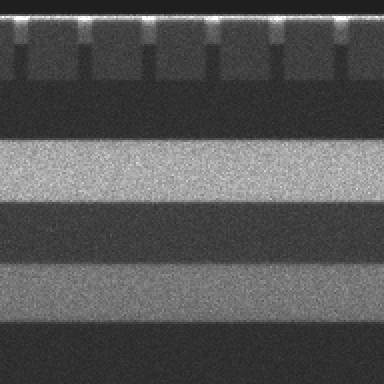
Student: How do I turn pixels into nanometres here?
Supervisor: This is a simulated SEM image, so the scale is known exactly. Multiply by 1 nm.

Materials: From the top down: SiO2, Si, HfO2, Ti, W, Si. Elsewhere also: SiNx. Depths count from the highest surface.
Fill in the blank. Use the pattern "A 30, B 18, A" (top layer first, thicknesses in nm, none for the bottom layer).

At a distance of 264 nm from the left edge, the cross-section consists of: SiNx 64, Si 60, HfO2 62, Ti 62, W 58, Si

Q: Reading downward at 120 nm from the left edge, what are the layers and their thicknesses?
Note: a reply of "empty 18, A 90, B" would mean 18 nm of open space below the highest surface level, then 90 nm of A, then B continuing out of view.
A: SiNx 64, Si 60, HfO2 62, Ti 62, W 58, Si